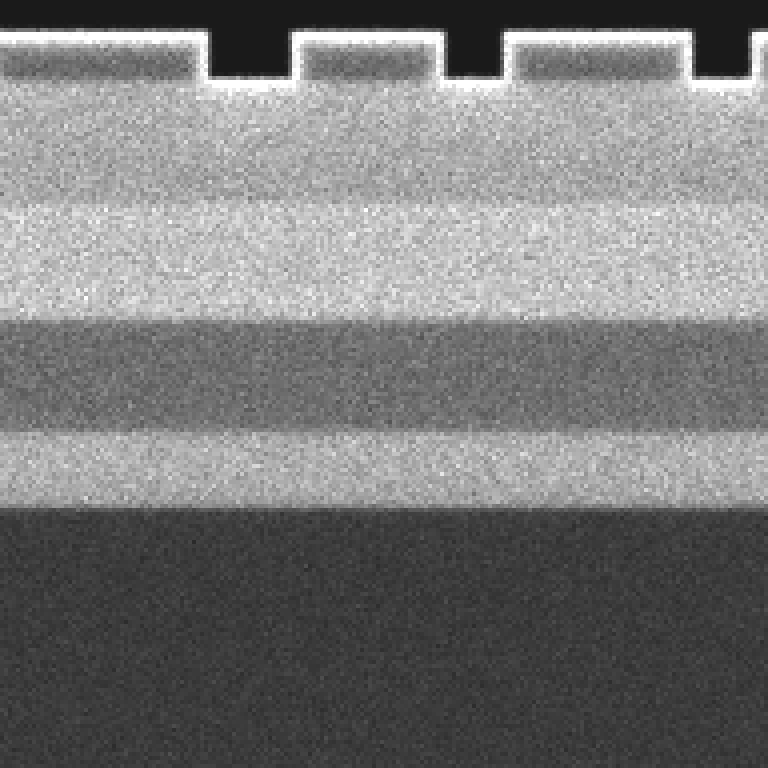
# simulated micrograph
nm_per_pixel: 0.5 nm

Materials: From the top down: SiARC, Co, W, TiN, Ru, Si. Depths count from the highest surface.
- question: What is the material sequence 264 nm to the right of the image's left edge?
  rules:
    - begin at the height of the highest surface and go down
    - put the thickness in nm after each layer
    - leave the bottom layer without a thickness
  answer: SiARC 24, Co 62, W 58, TiN 56, Ru 38, Si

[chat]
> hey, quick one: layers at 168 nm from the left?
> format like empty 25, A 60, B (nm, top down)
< SiARC 24, Co 62, W 58, TiN 56, Ru 38, Si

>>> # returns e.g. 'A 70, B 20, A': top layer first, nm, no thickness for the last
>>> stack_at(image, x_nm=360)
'empty 24, Co 62, W 58, TiN 56, Ru 38, Si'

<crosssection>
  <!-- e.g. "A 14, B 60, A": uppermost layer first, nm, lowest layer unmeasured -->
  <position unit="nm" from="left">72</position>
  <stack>SiARC 24, Co 62, W 58, TiN 56, Ru 38, Si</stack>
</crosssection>